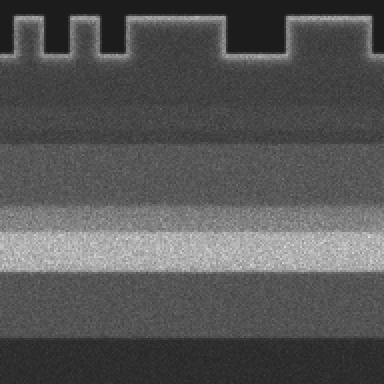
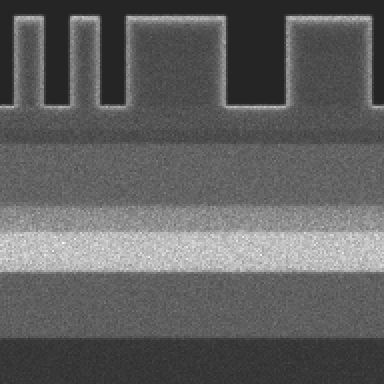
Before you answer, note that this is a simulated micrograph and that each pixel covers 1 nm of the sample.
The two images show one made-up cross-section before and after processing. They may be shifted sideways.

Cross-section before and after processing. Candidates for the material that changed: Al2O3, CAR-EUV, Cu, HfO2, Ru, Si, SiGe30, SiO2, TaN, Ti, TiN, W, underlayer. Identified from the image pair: underlayer (removed).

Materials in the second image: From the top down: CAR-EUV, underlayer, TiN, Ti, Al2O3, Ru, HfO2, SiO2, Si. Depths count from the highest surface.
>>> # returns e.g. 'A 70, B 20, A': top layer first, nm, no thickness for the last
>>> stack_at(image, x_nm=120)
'empty 90, TiN 24, Ti 14, Al2O3 62, Ru 26, HfO2 40, SiO2 66, Si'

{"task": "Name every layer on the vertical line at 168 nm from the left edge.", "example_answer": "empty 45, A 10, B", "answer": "CAR-EUV 38, underlayer 52, TiN 24, Ti 14, Al2O3 62, Ru 26, HfO2 40, SiO2 66, Si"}